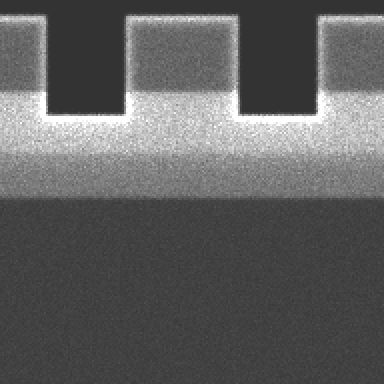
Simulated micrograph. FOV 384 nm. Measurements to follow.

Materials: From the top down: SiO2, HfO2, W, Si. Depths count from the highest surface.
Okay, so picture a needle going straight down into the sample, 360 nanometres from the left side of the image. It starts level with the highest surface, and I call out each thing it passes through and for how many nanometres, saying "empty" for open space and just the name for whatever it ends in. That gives SiO2 76, HfO2 60, W 46, Si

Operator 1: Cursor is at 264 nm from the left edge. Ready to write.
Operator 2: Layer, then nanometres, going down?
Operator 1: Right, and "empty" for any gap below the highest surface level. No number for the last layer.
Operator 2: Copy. empty 100, HfO2 36, W 46, Si